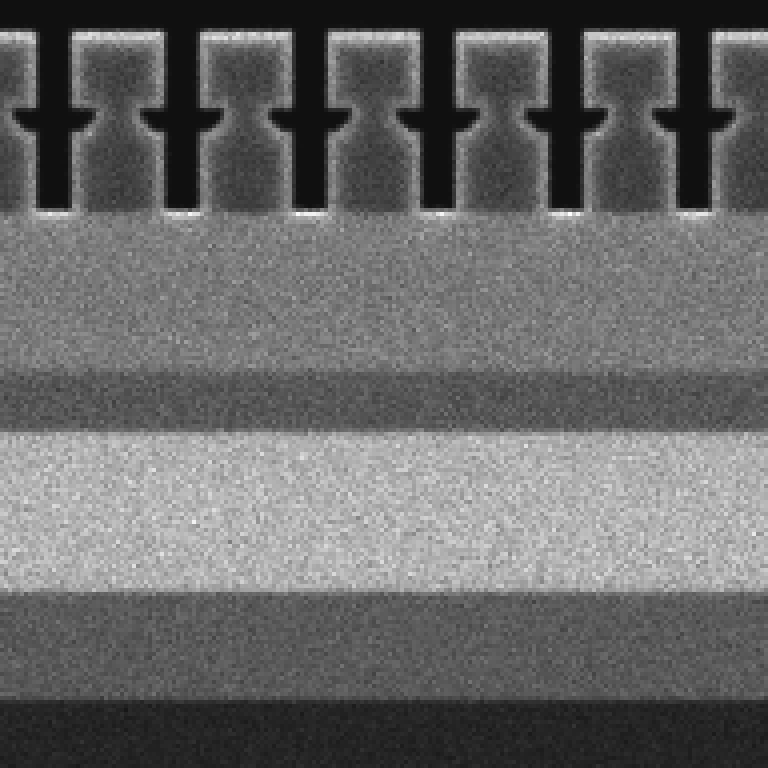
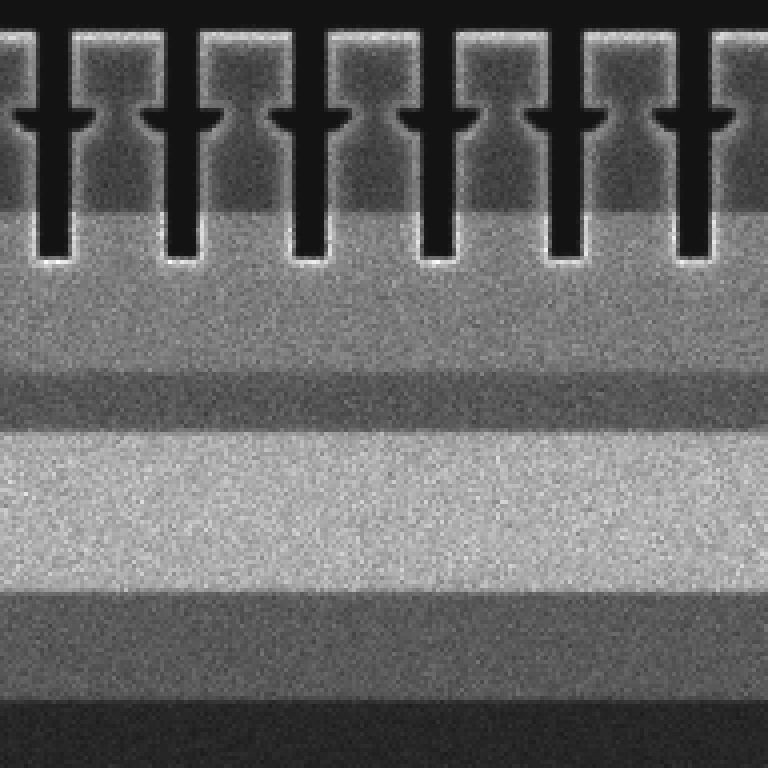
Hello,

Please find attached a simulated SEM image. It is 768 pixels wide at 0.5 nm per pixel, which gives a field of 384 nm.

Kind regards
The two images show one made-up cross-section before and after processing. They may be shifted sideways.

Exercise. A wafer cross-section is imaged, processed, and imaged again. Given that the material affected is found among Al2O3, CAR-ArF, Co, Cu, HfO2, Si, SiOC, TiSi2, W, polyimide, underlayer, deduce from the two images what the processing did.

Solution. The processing removed W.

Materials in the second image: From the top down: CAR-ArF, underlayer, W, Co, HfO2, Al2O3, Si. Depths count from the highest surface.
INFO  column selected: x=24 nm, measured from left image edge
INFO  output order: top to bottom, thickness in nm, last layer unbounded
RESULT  empty 114, W 56, Co 30, HfO2 80, Al2O3 54, Si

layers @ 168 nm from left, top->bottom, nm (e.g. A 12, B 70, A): CAR-ArF 38, empty 12, underlayer 40, W 80, Co 30, HfO2 80, Al2O3 54, Si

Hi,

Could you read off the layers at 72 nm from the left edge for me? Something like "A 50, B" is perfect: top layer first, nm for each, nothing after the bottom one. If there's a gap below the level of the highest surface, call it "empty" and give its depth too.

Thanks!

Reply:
CAR-ArF 38, empty 8, underlayer 44, W 80, Co 30, HfO2 80, Al2O3 54, Si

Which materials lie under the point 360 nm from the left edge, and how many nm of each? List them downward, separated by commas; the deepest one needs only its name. CAR-ArF 38, empty 12, underlayer 40, W 80, Co 30, HfO2 80, Al2O3 54, Si